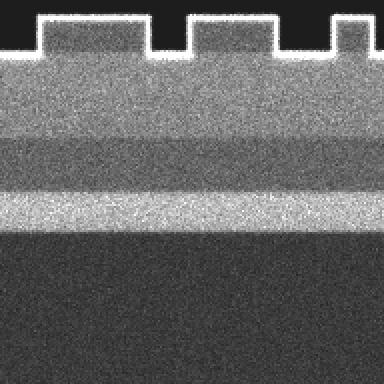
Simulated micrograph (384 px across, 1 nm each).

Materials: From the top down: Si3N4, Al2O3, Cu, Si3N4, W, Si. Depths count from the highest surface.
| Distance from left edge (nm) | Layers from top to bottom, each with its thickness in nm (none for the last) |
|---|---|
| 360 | Si3N4 36, Al2O3 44, Cu 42, Si3N4 54, W 40, Si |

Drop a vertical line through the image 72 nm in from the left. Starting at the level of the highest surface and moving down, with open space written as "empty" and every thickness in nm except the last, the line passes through Si3N4 36, Al2O3 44, Cu 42, Si3N4 54, W 40, Si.